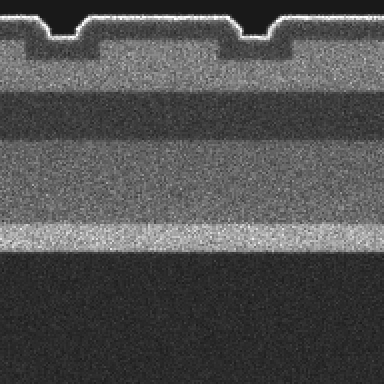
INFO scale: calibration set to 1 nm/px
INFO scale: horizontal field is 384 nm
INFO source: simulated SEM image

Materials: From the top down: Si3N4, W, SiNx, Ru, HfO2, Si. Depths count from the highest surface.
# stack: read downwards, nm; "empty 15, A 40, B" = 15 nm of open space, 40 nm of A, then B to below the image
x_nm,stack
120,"Si3N4 24, W 52, SiNx 48, Ru 84, HfO2 28, Si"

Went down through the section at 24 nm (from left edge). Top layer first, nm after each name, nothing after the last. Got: Si3N4 24, W 52, SiNx 48, Ru 84, HfO2 28, Si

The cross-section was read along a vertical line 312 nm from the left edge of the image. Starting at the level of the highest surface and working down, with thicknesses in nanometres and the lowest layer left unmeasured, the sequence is Si3N4 24, W 52, SiNx 48, Ru 84, HfO2 28, Si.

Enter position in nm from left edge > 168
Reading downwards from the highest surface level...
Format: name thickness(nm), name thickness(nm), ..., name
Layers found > Si3N4 24, W 52, SiNx 48, Ru 84, HfO2 28, Si